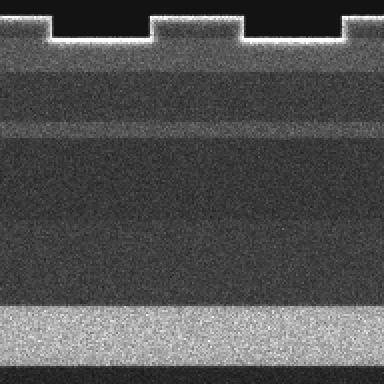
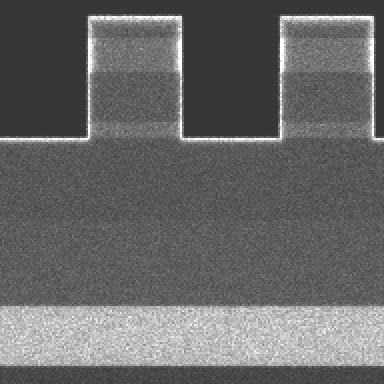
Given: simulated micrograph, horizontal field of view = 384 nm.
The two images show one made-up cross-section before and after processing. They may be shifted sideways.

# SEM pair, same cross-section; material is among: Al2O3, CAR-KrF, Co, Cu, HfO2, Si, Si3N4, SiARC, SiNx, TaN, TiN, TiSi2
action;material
removed;Al2O3 and Co and TiN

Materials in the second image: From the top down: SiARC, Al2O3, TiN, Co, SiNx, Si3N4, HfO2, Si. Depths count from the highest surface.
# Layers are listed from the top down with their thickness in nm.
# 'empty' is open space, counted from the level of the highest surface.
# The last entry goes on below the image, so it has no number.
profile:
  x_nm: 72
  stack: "empty 122, SiNx 82, Si3N4 86, HfO2 60, Si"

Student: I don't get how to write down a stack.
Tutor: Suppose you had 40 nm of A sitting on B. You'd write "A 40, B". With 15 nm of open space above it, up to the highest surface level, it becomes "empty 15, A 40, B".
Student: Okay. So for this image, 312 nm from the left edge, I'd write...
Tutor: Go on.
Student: SiARC 22, Al2O3 34, TiN 50, Co 16, SiNx 82, Si3N4 86, HfO2 60, Si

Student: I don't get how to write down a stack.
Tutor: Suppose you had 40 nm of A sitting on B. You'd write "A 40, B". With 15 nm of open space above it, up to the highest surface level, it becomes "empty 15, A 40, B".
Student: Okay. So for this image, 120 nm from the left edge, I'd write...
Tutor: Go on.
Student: SiARC 22, Al2O3 34, TiN 50, Co 16, SiNx 82, Si3N4 86, HfO2 60, Si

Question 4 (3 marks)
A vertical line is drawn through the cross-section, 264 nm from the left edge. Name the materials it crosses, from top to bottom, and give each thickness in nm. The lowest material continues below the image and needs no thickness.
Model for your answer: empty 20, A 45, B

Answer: empty 122, SiNx 82, Si3N4 86, HfO2 60, Si